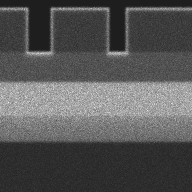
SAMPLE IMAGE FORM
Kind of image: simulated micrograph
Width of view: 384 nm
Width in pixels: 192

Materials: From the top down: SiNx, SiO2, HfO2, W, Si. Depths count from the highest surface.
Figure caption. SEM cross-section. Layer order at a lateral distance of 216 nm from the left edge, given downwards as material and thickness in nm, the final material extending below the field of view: SiNx 88, SiO2 60, HfO2 68, W 52, Si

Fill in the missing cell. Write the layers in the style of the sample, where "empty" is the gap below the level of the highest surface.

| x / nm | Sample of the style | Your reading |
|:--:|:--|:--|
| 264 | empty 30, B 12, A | SiNx 88, SiO2 60, HfO2 68, W 52, Si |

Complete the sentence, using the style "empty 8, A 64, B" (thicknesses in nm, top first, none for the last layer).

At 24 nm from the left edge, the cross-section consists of SiNx 88, SiO2 60, HfO2 68, W 52, Si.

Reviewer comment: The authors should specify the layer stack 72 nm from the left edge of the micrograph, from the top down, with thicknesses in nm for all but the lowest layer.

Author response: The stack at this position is empty 88, SiO2 60, HfO2 68, W 52, Si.